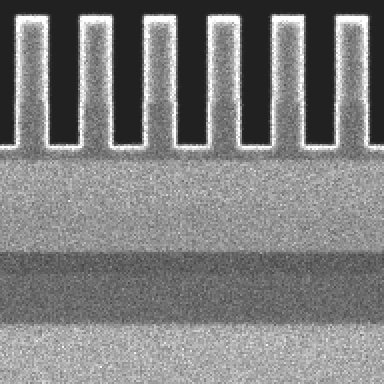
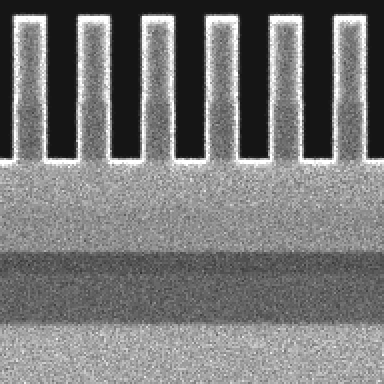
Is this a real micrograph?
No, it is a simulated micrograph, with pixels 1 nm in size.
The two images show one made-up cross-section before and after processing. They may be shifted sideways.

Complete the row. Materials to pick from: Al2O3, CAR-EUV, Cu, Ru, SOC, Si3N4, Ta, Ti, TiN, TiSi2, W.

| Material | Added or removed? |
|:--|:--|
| TiN | removed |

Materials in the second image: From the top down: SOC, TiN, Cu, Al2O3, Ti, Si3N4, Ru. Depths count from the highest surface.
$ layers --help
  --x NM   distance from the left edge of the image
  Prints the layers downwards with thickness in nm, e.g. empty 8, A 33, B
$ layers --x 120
empty 144, Cu 48, Al2O3 44, Ti 22, Si3N4 50, Ru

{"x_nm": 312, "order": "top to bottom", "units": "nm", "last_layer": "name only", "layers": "empty 144, Cu 48, Al2O3 44, Ti 22, Si3N4 50, Ru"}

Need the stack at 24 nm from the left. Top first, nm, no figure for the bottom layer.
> SOC 86, TiN 58, Cu 48, Al2O3 44, Ti 22, Si3N4 50, Ru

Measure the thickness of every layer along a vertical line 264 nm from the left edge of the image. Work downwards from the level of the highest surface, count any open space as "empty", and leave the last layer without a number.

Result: empty 144, Cu 48, Al2O3 44, Ti 22, Si3N4 50, Ru